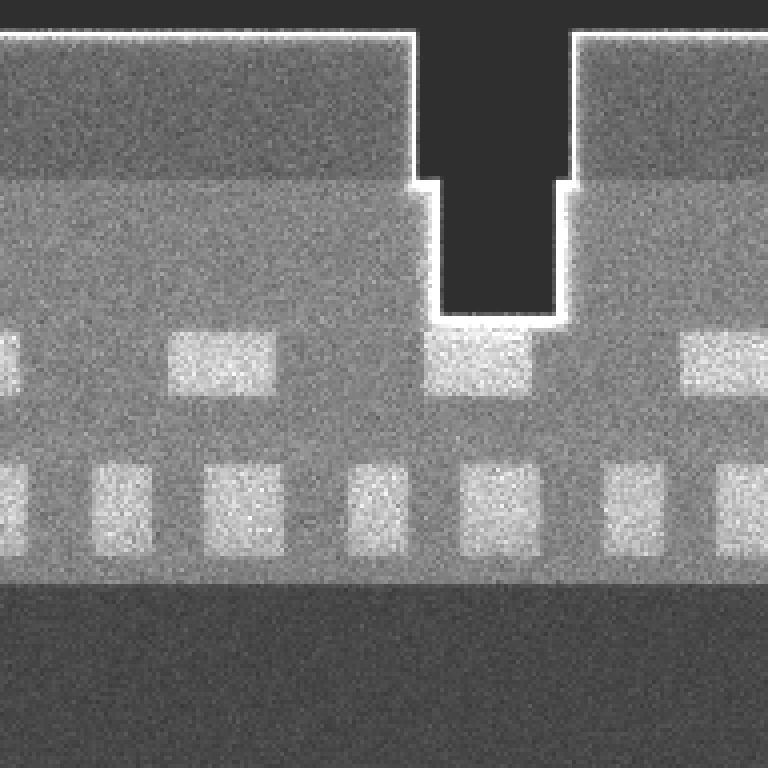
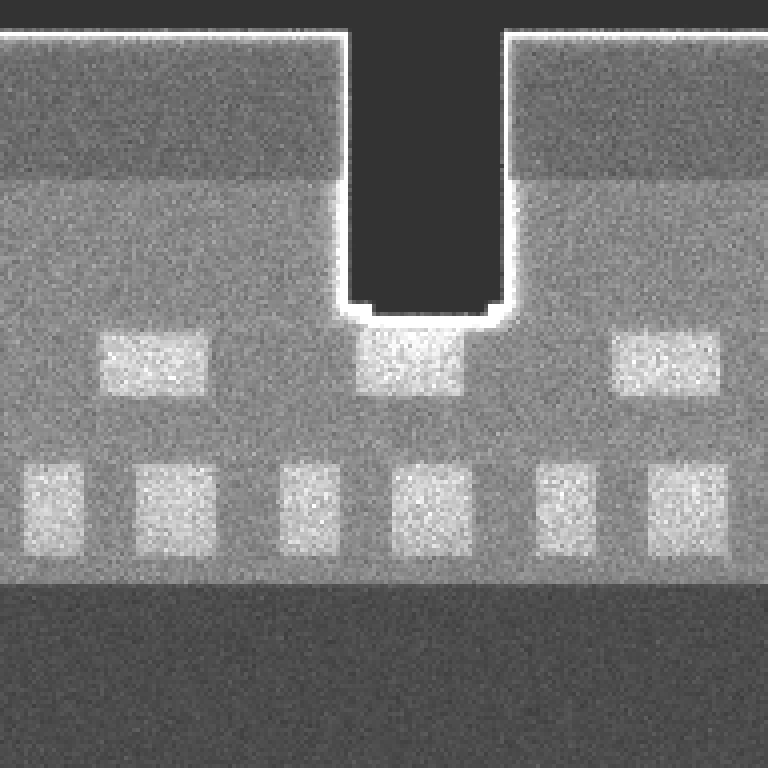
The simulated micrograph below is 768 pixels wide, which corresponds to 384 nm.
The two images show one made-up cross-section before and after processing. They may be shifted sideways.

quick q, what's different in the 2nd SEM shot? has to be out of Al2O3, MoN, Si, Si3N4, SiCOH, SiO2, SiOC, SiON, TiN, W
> SiO2 removed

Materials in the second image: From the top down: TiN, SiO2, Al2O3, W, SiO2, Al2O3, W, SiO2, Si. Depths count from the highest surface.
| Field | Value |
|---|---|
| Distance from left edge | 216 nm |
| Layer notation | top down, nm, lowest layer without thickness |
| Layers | empty 142, Al2O3 8, W 32, SiO2 18, Al2O3 16, W 46, SiO2 14, Si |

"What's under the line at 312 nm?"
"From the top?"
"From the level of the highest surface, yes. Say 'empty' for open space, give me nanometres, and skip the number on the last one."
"TiN 74, SiO2 68, Al2O3 8, W 32, SiO2 18, Al2O3 16, SiO2 60, Si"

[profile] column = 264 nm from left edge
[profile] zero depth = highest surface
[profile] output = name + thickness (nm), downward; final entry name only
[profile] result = TiN 74, SiO2 68, Al2O3 8, SiO2 50, Al2O3 16, SiO2 60, Si